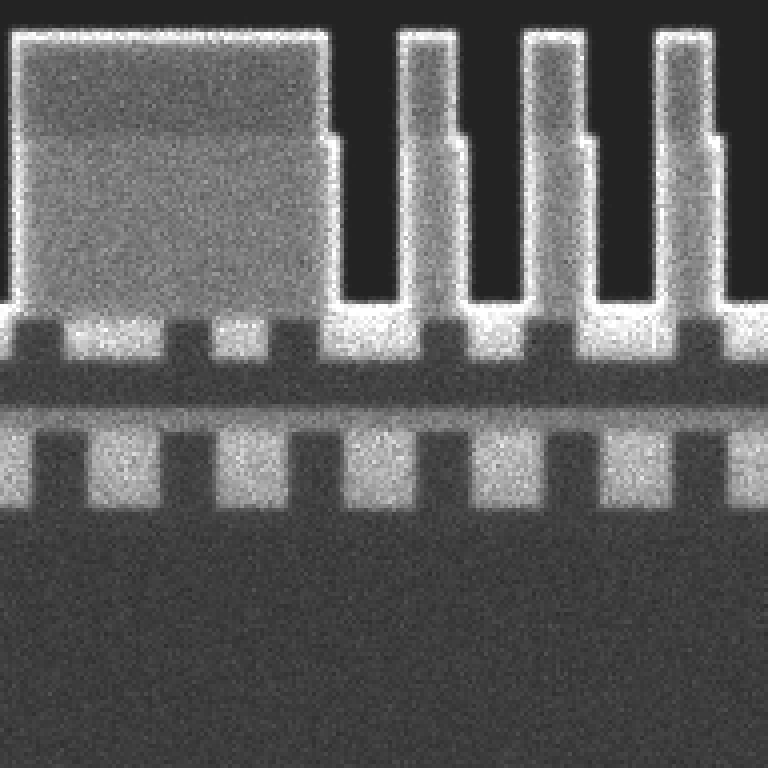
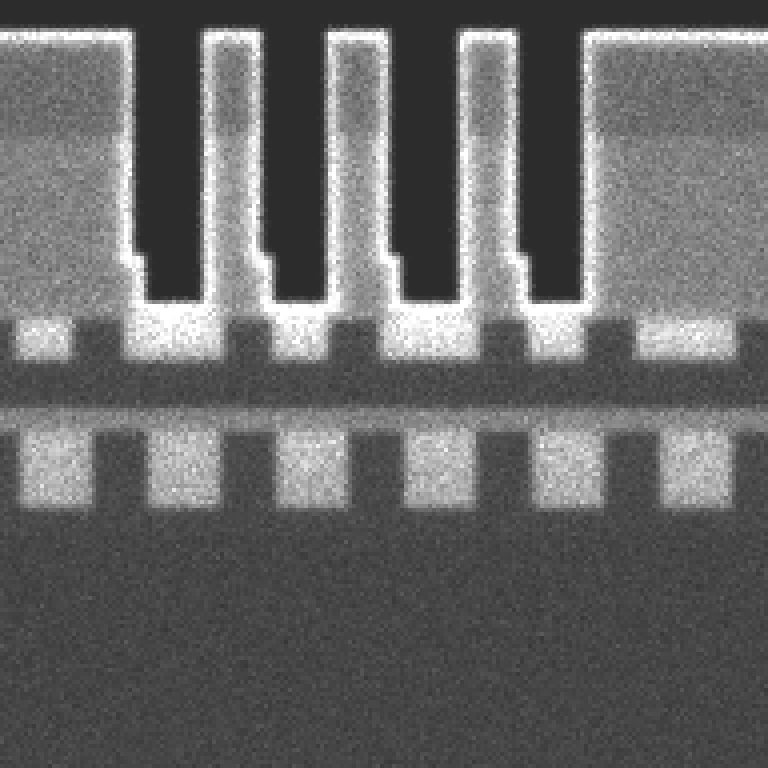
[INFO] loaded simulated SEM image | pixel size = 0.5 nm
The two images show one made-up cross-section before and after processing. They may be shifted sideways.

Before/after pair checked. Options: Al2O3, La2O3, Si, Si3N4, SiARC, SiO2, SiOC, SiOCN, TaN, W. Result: removed SiO2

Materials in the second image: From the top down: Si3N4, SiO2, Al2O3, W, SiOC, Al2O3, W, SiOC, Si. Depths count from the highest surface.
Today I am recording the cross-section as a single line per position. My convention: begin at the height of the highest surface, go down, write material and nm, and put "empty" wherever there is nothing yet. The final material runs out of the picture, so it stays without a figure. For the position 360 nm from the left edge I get Si3N4 52, SiO2 84, Al2O3 8, W 20, SiOC 24, Al2O3 12, W 38, SiOC 14, Si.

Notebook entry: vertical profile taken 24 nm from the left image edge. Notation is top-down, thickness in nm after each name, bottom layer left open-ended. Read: Si3N4 52, SiO2 84, Al2O3 8, W 20, SiOC 24, Al2O3 12, W 38, SiOC 14, Si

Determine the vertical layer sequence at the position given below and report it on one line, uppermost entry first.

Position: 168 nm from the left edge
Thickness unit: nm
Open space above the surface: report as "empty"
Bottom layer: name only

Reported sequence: Si3N4 52, SiO2 84, Al2O3 8, SiOC 44, Al2O3 12, W 38, SiOC 14, Si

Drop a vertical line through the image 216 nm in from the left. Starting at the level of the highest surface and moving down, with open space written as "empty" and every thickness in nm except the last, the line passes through empty 136, Al2O3 8, W 20, SiOC 24, Al2O3 12, W 38, SiOC 14, Si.